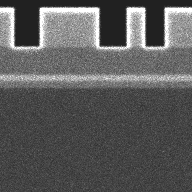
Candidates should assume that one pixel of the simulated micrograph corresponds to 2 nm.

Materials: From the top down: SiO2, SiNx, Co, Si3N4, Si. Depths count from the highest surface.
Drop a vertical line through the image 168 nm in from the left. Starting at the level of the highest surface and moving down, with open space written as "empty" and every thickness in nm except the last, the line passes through SiO2 78, SiNx 56, Co 12, Si3N4 14, Si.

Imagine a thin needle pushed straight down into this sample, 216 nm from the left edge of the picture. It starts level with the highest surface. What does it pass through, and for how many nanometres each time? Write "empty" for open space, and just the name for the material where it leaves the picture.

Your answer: empty 78, SiNx 56, Co 12, Si3N4 14, Si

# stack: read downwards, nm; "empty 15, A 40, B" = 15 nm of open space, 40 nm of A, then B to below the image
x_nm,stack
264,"SiO2 78, SiNx 56, Co 12, Si3N4 14, Si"